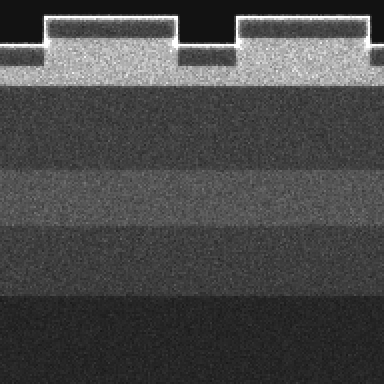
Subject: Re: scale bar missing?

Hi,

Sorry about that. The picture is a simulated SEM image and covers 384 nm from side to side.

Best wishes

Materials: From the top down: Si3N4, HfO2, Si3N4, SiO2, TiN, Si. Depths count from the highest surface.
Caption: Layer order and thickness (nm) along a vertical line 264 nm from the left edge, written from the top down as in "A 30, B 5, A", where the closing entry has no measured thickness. Si3N4 22, HfO2 48, Si3N4 84, SiO2 56, TiN 70, Si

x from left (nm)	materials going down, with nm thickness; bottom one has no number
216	empty 28, Si3N4 22, HfO2 20, Si3N4 84, SiO2 56, TiN 70, Si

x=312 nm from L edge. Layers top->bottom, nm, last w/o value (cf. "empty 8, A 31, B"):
Si3N4 22, HfO2 48, Si3N4 84, SiO2 56, TiN 70, Si